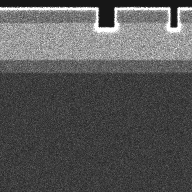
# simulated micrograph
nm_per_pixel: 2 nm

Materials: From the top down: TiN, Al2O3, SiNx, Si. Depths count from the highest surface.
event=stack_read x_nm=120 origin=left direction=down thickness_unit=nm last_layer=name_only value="TiN 30, Al2O3 74, SiNx 26, Si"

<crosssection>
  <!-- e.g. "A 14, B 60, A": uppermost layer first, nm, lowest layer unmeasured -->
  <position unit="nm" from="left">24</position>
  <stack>TiN 30, Al2O3 74, SiNx 26, Si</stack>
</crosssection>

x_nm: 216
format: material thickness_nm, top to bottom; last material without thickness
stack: empty 40, Al2O3 64, SiNx 26, Si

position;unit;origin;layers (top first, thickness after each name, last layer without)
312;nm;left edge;TiN 30, Al2O3 74, SiNx 26, Si